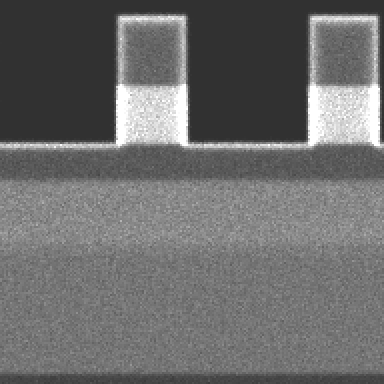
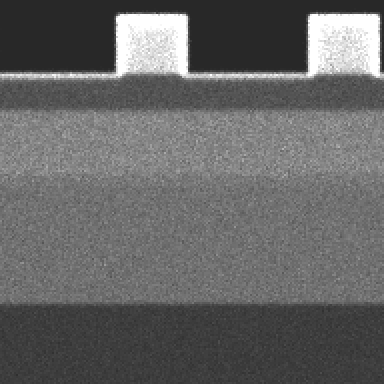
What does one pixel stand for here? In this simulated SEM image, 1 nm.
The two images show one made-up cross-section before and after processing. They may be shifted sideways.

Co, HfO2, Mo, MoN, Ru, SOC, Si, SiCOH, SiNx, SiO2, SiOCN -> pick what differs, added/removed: SOC removed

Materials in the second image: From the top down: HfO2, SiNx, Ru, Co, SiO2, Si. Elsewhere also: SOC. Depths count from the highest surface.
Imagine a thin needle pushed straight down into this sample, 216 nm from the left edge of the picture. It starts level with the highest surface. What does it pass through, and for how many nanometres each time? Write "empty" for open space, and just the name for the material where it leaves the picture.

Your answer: empty 58, SiNx 36, Ru 64, Co 12, SiO2 118, Si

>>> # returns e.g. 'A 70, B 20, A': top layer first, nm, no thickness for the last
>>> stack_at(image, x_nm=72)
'empty 58, SiNx 36, Ru 64, Co 12, SiO2 118, Si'